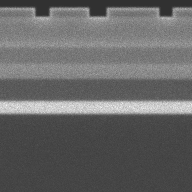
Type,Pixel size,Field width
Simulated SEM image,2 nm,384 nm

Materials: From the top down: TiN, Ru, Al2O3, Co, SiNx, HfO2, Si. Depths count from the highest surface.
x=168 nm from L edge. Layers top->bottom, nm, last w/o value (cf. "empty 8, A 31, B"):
TiN 18, Ru 60, Al2O3 34, Co 30, SiNx 44, HfO2 26, Si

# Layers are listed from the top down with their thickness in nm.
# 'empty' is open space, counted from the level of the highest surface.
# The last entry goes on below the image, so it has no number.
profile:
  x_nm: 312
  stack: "TiN 18, Ru 60, Al2O3 34, Co 30, SiNx 44, HfO2 26, Si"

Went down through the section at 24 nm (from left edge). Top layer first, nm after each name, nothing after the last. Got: TiN 18, Ru 60, Al2O3 34, Co 30, SiNx 44, HfO2 26, Si